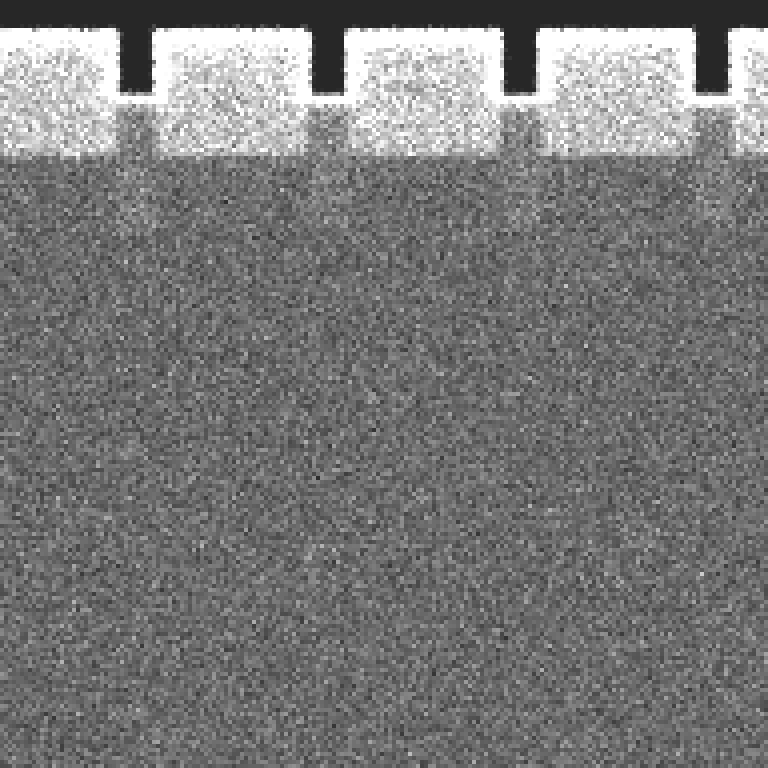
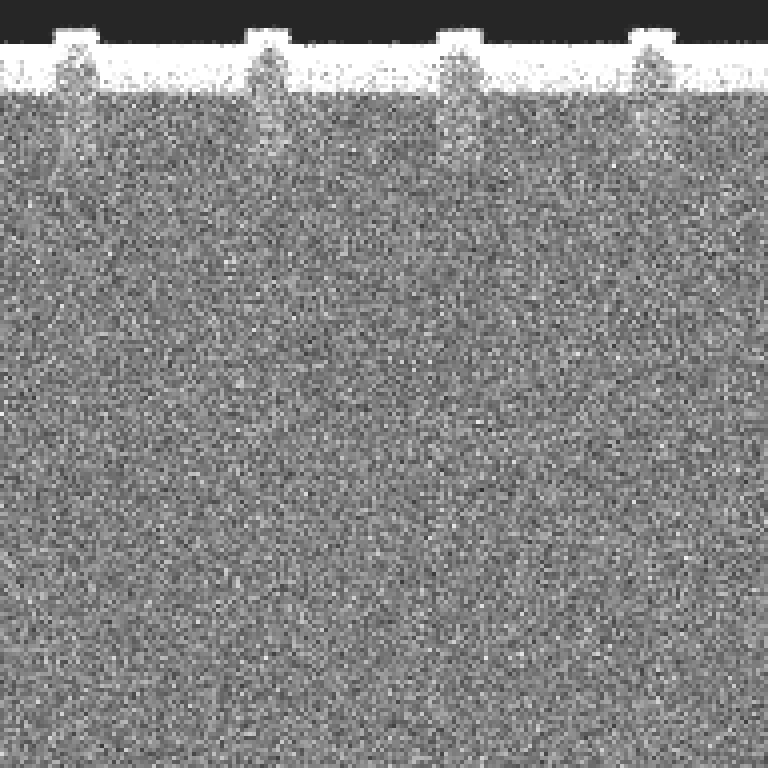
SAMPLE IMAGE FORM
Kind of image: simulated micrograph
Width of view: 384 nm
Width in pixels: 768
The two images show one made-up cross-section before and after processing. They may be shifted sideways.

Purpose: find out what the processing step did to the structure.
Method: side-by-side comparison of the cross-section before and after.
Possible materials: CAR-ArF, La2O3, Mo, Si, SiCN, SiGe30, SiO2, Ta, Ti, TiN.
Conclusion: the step removed TiN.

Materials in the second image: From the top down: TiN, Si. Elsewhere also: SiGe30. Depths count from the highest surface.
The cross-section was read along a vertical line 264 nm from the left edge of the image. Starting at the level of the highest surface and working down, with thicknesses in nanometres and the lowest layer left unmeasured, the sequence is empty 8, TiN 22, Si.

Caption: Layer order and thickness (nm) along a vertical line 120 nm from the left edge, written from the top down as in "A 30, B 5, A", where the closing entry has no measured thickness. empty 8, TiN 22, Si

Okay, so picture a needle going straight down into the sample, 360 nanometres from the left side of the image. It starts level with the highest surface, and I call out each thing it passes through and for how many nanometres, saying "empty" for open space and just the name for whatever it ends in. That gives empty 8, TiN 22, Si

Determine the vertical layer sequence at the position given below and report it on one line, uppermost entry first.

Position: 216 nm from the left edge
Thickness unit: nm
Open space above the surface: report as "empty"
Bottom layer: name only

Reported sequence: empty 8, TiN 22, Si